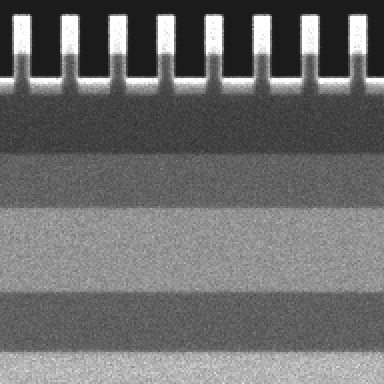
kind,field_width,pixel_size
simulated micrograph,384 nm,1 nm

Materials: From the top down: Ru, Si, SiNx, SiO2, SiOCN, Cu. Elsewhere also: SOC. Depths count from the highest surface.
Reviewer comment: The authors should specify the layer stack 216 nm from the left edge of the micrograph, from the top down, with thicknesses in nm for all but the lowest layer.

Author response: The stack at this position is Ru 38, Si 100, SiNx 54, SiO2 84, SiOCN 60, Cu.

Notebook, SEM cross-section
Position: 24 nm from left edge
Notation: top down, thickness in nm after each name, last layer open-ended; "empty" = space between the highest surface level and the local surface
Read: Ru 38, Si 100, SiNx 54, SiO2 84, SiOCN 60, Cu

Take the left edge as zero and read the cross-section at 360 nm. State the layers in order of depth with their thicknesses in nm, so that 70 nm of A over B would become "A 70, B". Ru 38, Si 100, SiNx 54, SiO2 84, SiOCN 60, Cu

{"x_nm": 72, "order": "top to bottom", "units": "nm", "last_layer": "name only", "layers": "Ru 38, Si 100, SiNx 54, SiO2 84, SiOCN 60, Cu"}